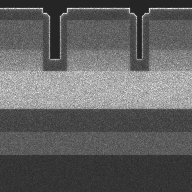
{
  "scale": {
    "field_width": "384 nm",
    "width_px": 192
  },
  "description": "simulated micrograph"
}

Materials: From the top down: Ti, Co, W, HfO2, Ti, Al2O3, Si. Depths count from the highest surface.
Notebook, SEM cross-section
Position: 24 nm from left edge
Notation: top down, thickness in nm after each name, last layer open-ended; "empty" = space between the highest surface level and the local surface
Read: Ti 24, Co 60, W 42, HfO2 76, Ti 46, Al2O3 46, Si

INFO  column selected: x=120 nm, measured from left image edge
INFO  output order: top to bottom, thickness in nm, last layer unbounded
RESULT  empty 16, Ti 110, HfO2 76, Ti 46, Al2O3 46, Si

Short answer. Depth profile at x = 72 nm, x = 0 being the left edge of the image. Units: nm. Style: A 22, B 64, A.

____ Ti 24, Co 60, W 42, HfO2 76, Ti 46, Al2O3 46, Si